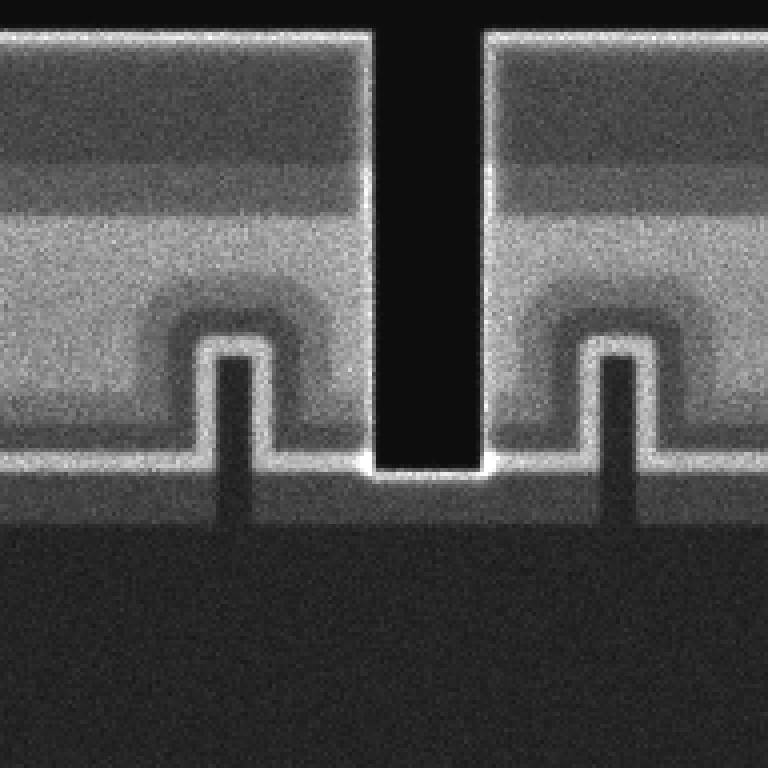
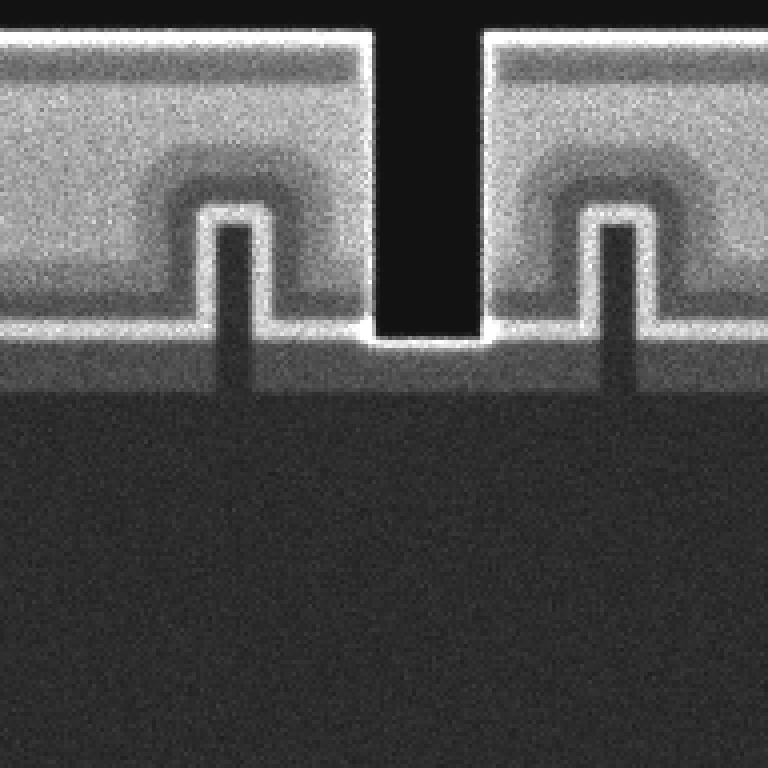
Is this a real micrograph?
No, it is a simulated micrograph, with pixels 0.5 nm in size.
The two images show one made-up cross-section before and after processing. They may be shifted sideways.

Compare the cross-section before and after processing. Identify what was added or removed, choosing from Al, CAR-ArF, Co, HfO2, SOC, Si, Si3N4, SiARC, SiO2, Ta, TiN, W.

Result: SOC removed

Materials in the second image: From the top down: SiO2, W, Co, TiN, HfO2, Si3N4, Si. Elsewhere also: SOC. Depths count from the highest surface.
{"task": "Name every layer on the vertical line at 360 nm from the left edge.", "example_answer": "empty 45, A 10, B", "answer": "SiO2 26, W 88, Co 16, TiN 14, HfO2 10, Si3N4 26, Si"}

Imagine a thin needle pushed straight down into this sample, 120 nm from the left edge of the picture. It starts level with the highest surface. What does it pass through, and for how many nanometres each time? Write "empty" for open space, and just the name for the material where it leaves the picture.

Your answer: SiO2 26, W 30, Co 16, TiN 14, HfO2 10, Si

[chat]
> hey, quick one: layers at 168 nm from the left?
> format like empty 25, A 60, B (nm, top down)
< SiO2 26, W 88, Co 16, TiN 14, HfO2 10, Si3N4 26, Si